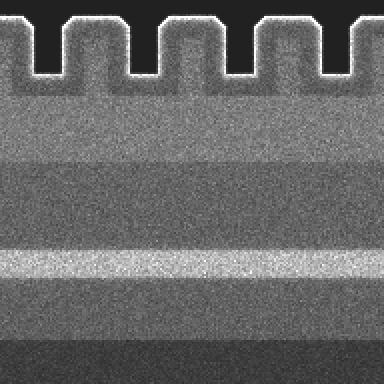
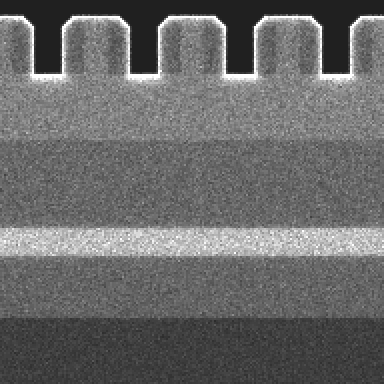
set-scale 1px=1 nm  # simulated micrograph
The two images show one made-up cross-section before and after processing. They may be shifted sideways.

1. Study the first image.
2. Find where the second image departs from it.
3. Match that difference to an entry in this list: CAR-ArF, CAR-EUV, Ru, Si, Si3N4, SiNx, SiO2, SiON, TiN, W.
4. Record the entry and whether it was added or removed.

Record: SiNx / removed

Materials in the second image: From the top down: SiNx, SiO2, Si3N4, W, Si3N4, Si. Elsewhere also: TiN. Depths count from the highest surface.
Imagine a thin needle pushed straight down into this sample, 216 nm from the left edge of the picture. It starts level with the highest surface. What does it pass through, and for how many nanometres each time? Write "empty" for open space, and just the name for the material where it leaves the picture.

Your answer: empty 2, SiNx 56, SiO2 66, Si3N4 88, W 28, Si3N4 62, Si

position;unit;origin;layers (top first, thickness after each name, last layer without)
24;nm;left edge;empty 2, SiNx 56, SiO2 66, Si3N4 88, W 28, Si3N4 62, Si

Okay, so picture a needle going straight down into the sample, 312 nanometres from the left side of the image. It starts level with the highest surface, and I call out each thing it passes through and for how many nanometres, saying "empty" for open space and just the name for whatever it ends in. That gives empty 2, SiNx 56, SiO2 66, Si3N4 88, W 28, Si3N4 62, Si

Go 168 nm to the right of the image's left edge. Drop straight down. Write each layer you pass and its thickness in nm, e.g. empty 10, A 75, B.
SiNx 58, SiO2 66, Si3N4 88, W 28, Si3N4 62, Si